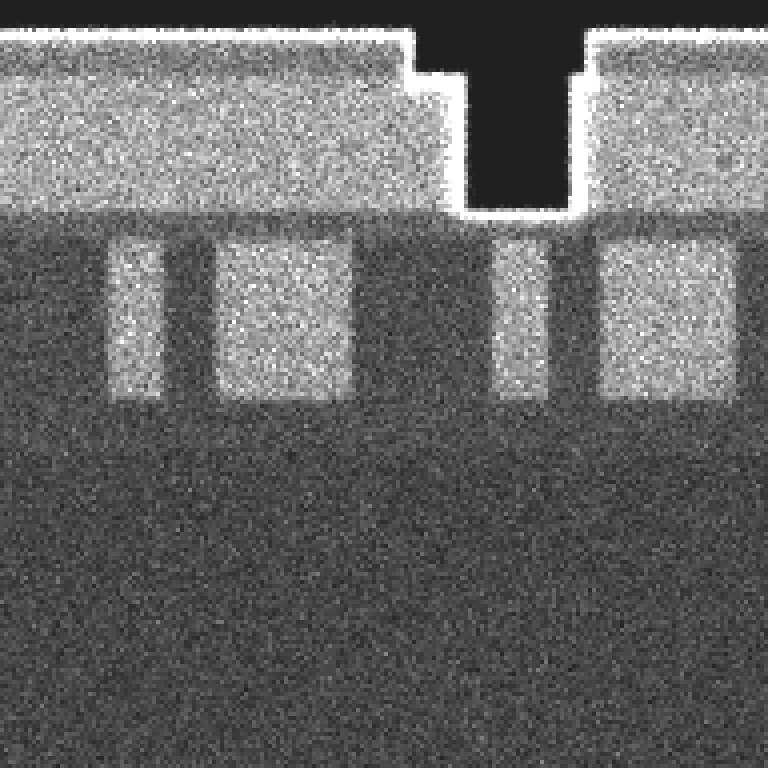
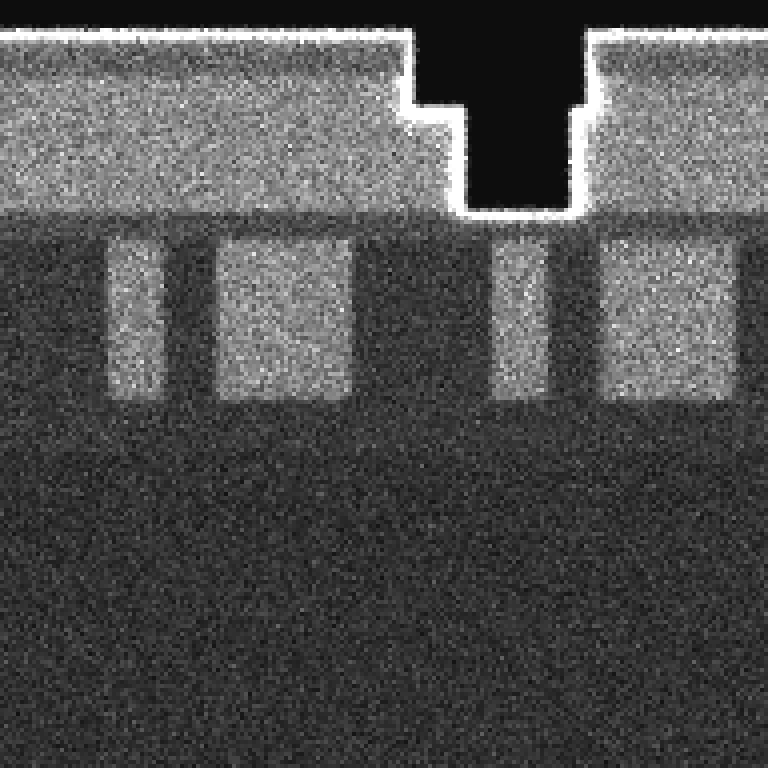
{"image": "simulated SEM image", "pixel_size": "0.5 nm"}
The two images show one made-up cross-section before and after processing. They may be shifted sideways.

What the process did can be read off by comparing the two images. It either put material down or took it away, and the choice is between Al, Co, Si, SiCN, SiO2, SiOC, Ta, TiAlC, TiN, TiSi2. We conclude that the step removed SiO2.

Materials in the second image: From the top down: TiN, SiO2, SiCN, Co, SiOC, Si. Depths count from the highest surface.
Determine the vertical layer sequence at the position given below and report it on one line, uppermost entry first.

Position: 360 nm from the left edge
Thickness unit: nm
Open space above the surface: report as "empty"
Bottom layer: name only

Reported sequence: TiN 22, SiO2 68, SiCN 14, Co 80, SiOC 26, Si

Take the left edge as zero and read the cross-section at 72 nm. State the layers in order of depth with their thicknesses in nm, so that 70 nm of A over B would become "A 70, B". TiN 22, SiO2 68, SiCN 14, Co 80, SiOC 26, Si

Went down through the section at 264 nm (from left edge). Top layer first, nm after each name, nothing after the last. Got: empty 90, SiCN 14, Co 80, SiOC 26, Si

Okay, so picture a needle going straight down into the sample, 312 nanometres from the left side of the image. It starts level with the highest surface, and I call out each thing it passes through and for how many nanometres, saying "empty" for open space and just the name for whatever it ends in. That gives TiN 22, SiO2 68, SiCN 14, Co 80, SiOC 26, Si